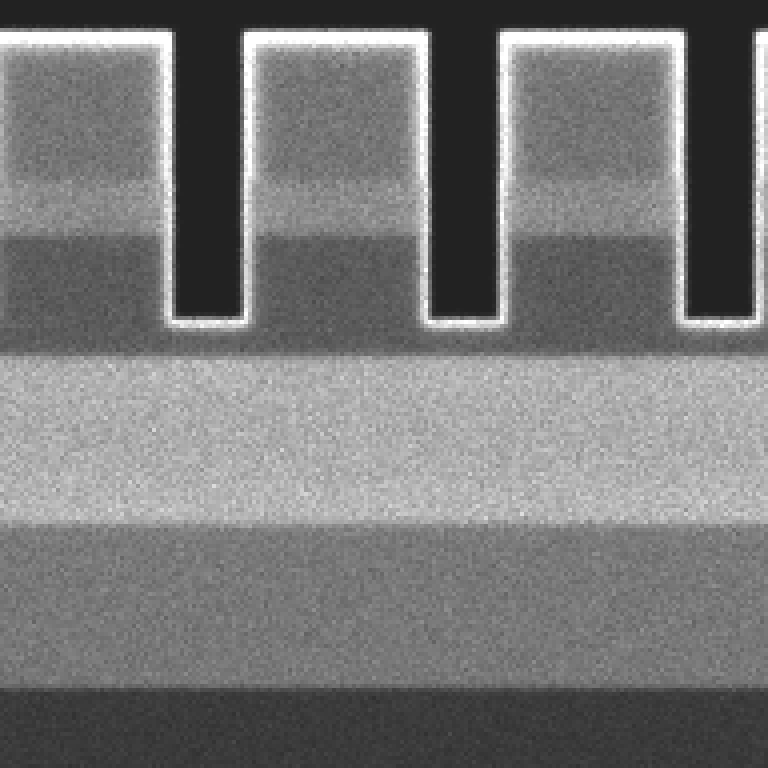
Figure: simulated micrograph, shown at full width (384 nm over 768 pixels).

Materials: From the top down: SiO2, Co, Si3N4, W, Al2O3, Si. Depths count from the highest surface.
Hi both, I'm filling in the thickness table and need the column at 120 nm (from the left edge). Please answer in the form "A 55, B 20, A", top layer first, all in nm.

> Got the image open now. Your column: empty 144, Si3N4 18, W 84, Al2O3 82, Si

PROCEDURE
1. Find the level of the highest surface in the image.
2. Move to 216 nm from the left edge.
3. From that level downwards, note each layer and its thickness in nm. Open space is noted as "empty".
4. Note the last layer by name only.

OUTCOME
empty 144, Si3N4 18, W 84, Al2O3 82, Si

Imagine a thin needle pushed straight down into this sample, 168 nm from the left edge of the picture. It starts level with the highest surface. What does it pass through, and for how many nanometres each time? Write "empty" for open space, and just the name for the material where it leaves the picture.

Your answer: SiO2 74, Co 28, Si3N4 60, W 84, Al2O3 82, Si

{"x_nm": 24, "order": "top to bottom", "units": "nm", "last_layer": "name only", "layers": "SiO2 74, Co 28, Si3N4 60, W 84, Al2O3 82, Si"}